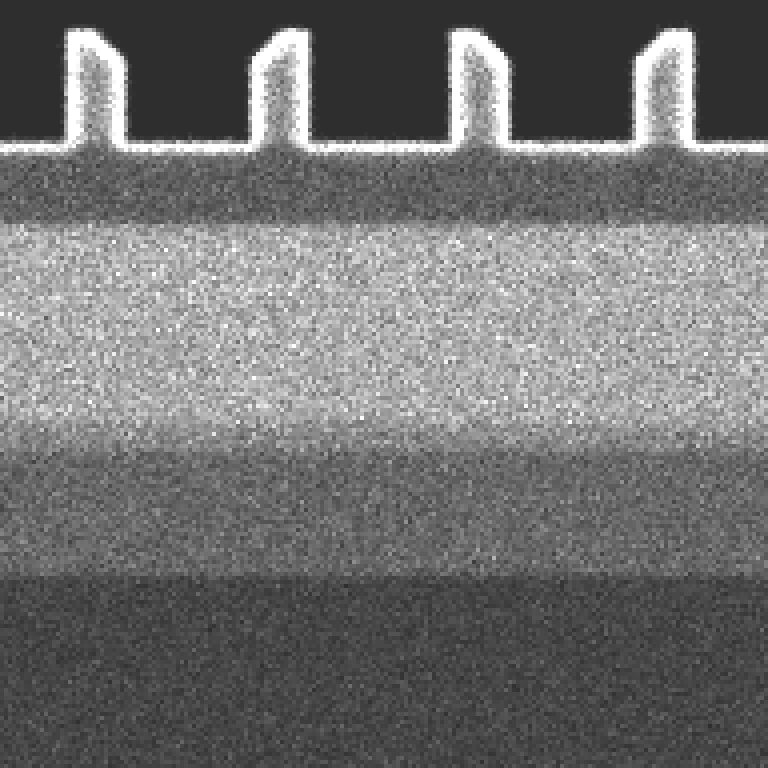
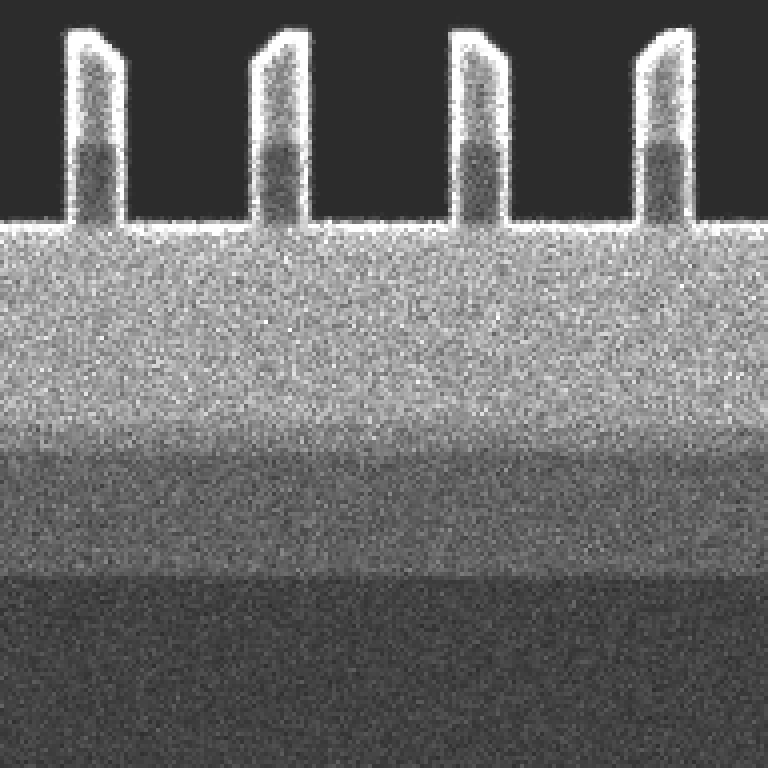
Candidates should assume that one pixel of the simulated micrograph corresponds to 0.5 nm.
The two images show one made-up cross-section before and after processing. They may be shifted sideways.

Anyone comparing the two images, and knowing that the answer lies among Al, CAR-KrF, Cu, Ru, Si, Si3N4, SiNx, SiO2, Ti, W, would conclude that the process removed SiNx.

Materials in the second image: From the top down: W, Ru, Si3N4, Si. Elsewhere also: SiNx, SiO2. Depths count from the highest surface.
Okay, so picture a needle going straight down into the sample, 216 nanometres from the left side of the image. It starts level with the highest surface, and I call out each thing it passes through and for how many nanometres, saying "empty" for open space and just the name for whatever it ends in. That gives empty 96, W 100, Ru 14, Si3N4 62, Si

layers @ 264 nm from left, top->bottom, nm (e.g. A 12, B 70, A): empty 96, W 100, Ru 14, Si3N4 62, Si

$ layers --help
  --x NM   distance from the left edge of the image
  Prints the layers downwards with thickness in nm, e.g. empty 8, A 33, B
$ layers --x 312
empty 96, W 100, Ru 14, Si3N4 62, Si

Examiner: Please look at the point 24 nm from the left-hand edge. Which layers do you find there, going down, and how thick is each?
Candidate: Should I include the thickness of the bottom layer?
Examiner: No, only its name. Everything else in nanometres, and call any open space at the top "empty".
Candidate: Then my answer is empty 96, W 100, Ru 14, Si3N4 62, Si